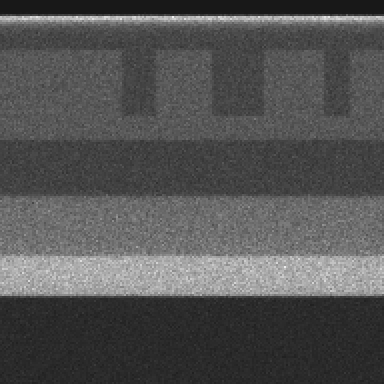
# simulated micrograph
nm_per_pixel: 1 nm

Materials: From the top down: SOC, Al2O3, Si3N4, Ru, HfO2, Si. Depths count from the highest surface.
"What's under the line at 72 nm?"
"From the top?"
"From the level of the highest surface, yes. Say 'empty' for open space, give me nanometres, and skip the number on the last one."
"SOC 34, Al2O3 90, Si3N4 56, Ru 60, HfO2 40, Si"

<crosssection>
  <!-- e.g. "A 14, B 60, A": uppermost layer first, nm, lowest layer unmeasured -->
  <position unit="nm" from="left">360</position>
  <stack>SOC 34, Al2O3 90, Si3N4 56, Ru 60, HfO2 40, Si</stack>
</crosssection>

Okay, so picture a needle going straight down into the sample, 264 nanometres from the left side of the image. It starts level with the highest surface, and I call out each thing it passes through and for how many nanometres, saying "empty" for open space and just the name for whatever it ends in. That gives SOC 34, Al2O3 90, Si3N4 56, Ru 60, HfO2 40, Si